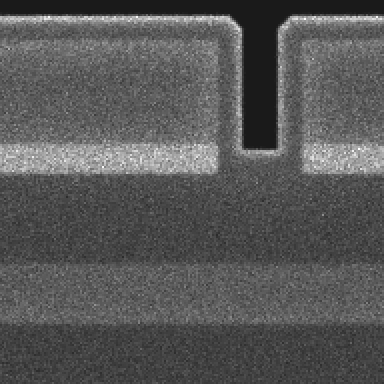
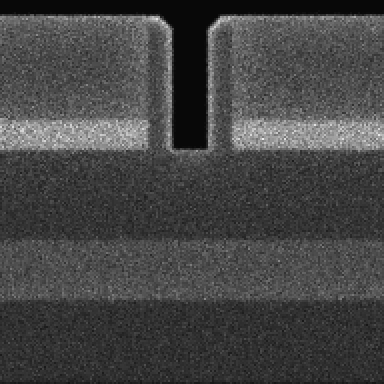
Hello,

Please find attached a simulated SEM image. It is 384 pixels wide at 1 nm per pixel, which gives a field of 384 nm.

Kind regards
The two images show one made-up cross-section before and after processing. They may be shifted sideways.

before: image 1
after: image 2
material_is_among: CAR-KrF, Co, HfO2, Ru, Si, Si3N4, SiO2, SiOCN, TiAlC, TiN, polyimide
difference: SiO2, removed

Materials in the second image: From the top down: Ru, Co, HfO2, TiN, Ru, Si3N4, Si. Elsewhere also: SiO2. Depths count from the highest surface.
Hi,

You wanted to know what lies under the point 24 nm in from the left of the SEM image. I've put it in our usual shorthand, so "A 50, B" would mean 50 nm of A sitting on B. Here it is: Ru 34, Co 70, HfO2 30, TiN 90, Ru 60, Si3N4 82, Si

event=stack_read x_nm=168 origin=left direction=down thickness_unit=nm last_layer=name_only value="empty 10, SiO2 124, TiN 90, Ru 60, Si3N4 82, Si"